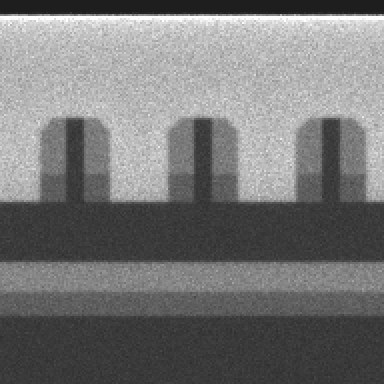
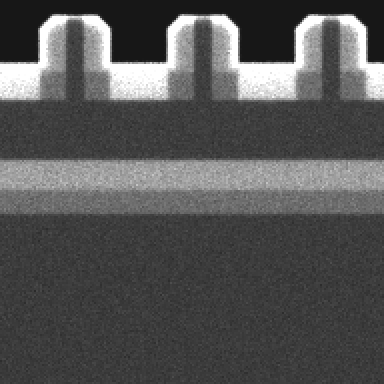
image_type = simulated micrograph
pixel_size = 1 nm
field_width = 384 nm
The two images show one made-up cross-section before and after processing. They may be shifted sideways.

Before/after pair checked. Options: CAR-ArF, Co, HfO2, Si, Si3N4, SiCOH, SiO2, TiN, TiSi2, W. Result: removed W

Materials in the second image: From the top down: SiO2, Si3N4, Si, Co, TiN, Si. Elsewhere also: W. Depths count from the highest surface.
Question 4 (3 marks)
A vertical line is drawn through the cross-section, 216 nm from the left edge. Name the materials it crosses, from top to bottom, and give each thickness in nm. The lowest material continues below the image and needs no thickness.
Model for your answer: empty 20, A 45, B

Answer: SiO2 56, Si3N4 28, Si 60, Co 30, TiN 24, Si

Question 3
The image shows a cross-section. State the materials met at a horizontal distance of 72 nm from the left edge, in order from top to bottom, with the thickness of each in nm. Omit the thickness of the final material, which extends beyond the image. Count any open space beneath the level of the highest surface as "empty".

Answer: Si 144, Co 30, TiN 24, Si